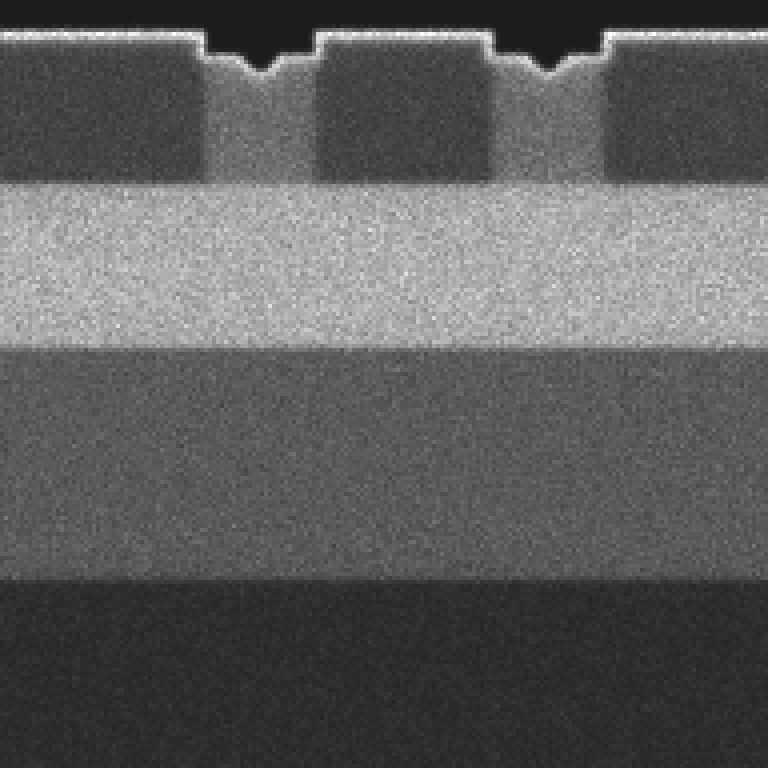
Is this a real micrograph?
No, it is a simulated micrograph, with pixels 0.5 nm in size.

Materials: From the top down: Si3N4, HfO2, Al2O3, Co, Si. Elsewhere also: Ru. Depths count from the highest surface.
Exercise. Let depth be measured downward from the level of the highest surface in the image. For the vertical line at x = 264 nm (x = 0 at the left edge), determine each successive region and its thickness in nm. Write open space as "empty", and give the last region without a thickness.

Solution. empty 14, Ru 62, HfO2 82, Al2O3 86, Co 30, Si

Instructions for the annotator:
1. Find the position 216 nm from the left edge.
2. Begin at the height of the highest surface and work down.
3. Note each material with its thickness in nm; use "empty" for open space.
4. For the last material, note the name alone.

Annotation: Si3N4 76, HfO2 82, Al2O3 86, Co 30, Si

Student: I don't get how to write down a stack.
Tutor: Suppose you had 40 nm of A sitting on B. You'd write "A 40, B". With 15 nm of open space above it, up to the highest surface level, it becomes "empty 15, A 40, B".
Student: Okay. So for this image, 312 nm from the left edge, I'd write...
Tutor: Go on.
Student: Si3N4 76, HfO2 82, Al2O3 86, Co 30, Si